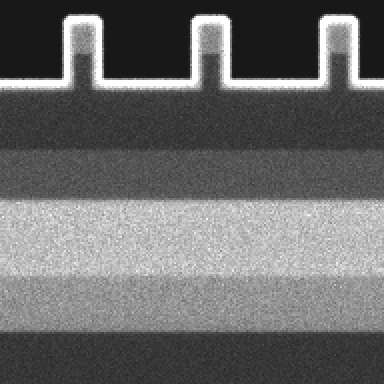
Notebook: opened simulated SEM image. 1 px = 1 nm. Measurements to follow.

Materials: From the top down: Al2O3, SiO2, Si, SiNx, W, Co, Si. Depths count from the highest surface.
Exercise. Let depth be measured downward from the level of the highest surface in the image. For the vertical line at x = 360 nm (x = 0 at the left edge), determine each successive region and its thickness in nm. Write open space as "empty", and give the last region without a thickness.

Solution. empty 64, Al2O3 10, Si 60, SiNx 50, W 76, Co 56, Si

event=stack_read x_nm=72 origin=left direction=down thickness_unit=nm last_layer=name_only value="Al2O3 74, Si 60, SiNx 50, W 76, Co 56, Si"